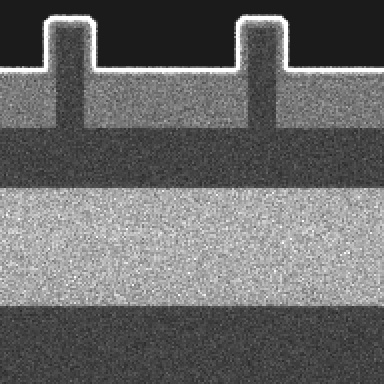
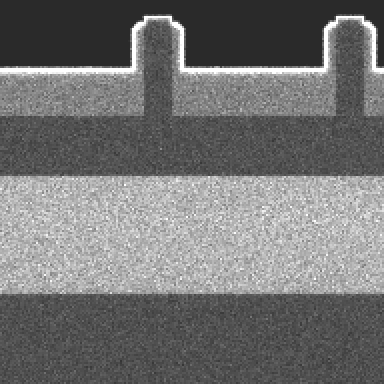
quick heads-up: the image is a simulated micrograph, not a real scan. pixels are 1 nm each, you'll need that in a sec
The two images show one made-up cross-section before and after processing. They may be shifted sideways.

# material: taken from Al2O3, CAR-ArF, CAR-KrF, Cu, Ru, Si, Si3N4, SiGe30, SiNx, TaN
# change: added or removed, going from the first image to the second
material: SiNx
change: removed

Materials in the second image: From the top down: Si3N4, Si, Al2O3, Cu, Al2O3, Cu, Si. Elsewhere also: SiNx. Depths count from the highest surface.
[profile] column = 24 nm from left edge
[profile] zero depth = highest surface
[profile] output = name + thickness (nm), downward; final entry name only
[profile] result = empty 52, Si3N4 48, Si 60, Al2O3 28, Cu 28, Al2O3 28, Cu 34, Si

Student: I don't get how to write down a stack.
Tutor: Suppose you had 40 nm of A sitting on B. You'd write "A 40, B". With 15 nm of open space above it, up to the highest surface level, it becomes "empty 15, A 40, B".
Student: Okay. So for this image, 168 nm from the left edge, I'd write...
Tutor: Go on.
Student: Si 160, Al2O3 28, Cu 28, Al2O3 28, Cu 34, Si